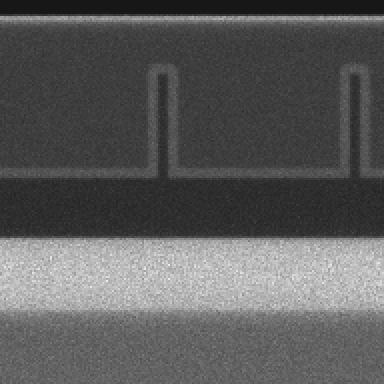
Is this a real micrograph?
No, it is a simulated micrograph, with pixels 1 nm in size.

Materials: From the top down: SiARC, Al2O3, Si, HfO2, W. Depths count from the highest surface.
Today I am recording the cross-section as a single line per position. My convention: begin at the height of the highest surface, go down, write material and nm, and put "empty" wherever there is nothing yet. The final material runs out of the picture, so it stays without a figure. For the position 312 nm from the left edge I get SiARC 152, Al2O3 10, Si 60, HfO2 72, W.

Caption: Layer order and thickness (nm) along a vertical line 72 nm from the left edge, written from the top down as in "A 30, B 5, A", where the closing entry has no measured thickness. SiARC 152, Al2O3 10, Si 60, HfO2 72, W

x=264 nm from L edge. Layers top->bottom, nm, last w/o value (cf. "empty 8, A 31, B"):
SiARC 152, Al2O3 10, Si 60, HfO2 72, W